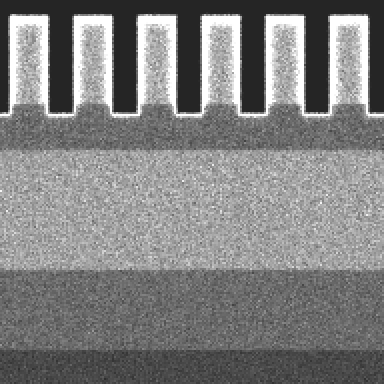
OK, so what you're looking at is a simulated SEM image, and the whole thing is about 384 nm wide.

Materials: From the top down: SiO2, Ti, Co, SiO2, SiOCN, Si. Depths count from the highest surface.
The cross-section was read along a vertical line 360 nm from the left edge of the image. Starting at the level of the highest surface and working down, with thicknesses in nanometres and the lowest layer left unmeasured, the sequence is SiO2 88, Ti 46, Co 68, SiO2 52, SiOCN 80, Si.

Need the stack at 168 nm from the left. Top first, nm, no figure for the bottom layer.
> SiO2 88, Ti 46, Co 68, SiO2 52, SiOCN 80, Si